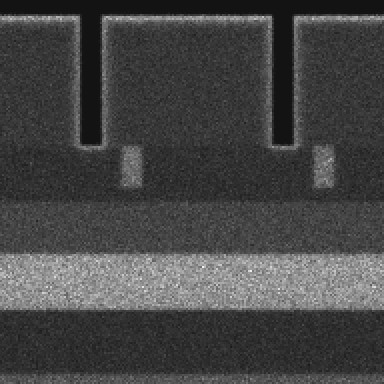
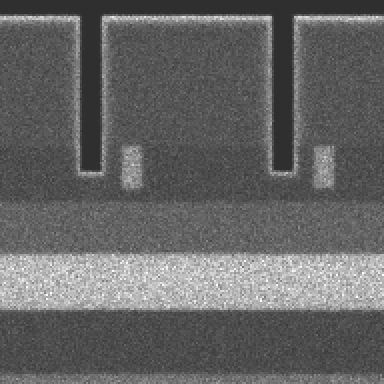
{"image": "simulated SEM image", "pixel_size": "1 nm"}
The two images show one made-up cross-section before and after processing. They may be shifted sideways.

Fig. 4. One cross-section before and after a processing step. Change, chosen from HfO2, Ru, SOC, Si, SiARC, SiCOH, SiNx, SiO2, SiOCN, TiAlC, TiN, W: SiNx removed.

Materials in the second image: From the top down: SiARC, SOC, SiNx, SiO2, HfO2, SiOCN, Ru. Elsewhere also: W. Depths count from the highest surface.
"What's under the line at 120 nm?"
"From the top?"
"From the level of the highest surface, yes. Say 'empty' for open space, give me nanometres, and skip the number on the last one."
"SiARC 26, SOC 104, SiNx 56, SiO2 52, HfO2 56, SiOCN 64, Ru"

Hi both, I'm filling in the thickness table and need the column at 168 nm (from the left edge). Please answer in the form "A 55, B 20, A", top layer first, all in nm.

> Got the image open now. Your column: SiARC 26, SOC 104, SiNx 56, SiO2 52, HfO2 56, SiOCN 64, Ru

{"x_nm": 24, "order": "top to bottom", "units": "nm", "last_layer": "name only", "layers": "SiARC 26, SOC 104, SiNx 56, SiO2 52, HfO2 56, SiOCN 64, Ru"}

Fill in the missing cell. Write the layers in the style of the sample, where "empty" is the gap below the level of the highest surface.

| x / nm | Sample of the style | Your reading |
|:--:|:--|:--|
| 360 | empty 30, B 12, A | SiARC 26, SOC 104, SiNx 56, SiO2 52, HfO2 56, SiOCN 64, Ru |